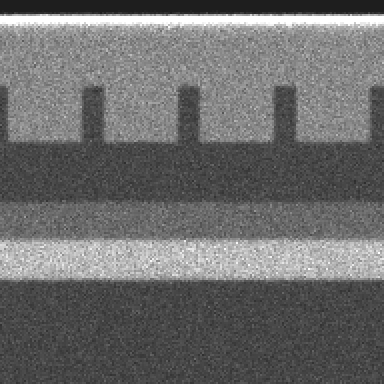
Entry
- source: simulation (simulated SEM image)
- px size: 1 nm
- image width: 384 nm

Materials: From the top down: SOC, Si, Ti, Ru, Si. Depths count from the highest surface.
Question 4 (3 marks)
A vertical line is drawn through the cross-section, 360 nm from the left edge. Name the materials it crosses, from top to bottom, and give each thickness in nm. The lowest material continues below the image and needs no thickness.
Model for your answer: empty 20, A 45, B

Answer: SOC 126, Si 60, Ti 38, Ru 40, Si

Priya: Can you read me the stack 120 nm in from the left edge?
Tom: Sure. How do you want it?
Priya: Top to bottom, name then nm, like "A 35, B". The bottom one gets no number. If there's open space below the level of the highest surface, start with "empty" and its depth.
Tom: SOC 126, Si 60, Ti 38, Ru 40, Si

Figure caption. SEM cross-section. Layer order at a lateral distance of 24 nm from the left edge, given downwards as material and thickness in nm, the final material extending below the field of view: SOC 126, Si 60, Ti 38, Ru 40, Si